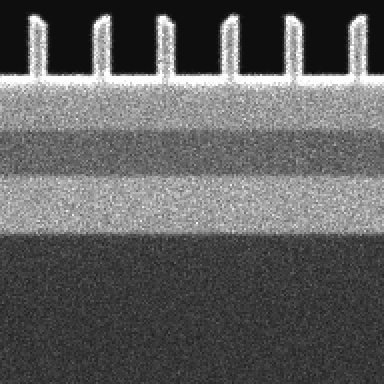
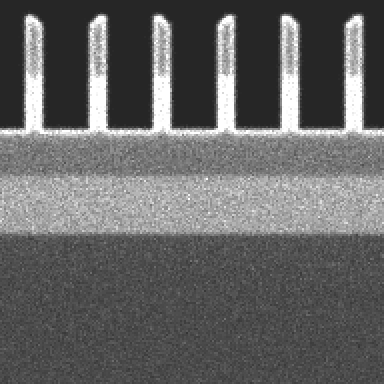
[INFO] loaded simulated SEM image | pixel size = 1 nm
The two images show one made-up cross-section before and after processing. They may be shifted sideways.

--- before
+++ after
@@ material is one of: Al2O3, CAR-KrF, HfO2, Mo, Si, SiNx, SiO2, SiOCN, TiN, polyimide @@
SiO2 removed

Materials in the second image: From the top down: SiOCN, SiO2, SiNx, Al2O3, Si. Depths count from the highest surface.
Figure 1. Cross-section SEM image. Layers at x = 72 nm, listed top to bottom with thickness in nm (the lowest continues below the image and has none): empty 114, SiNx 46, Al2O3 58, Si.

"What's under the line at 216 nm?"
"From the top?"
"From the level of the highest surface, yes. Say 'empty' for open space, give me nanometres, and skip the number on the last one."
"empty 114, SiNx 46, Al2O3 58, Si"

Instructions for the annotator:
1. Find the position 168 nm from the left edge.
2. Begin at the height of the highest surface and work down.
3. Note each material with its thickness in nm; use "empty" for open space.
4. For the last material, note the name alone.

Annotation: empty 8, SiOCN 52, SiO2 54, SiNx 46, Al2O3 58, Si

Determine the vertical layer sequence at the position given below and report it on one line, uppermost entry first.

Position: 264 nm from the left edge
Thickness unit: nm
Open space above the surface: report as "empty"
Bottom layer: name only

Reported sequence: empty 114, SiNx 46, Al2O3 58, Si